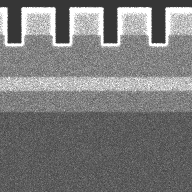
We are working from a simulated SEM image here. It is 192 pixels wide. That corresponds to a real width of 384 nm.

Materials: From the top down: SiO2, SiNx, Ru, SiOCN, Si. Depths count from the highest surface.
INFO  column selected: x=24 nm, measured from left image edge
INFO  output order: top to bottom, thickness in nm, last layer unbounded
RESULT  empty 72, SiNx 66, Ru 28, SiOCN 42, Si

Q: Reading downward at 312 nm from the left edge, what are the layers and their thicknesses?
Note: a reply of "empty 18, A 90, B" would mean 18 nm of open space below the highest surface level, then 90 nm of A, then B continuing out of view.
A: empty 72, SiNx 66, Ru 28, SiOCN 42, Si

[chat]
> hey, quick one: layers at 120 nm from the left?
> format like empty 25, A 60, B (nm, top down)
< empty 72, SiNx 66, Ru 28, SiOCN 42, Si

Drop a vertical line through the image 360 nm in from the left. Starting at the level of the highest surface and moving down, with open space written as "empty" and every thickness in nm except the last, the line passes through SiO2 54, SiNx 84, Ru 28, SiOCN 42, Si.